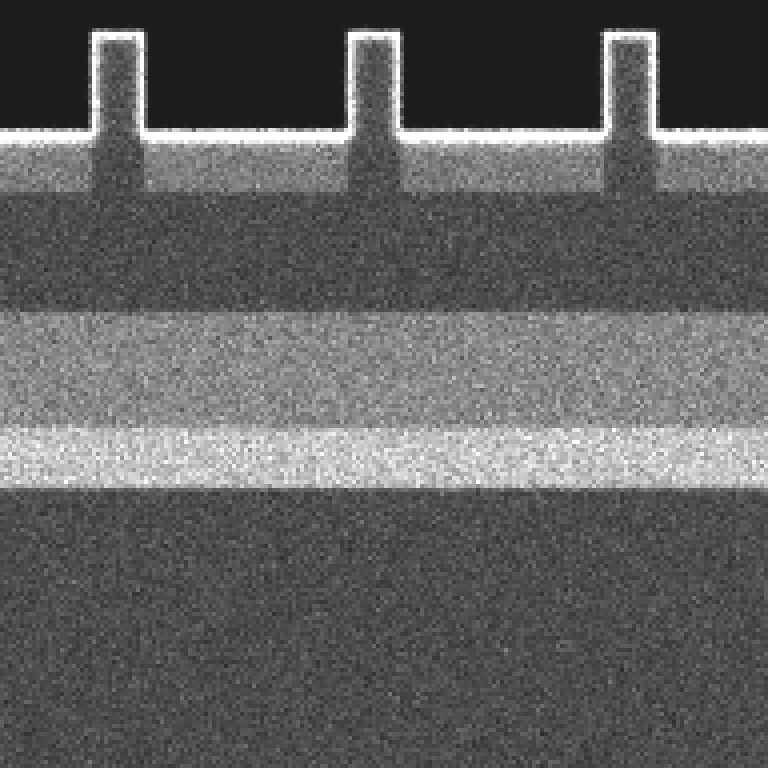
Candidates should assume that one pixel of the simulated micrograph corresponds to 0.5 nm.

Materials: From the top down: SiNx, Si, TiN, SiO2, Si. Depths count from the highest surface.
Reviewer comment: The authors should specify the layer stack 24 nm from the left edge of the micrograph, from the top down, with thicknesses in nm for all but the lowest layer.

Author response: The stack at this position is empty 50, SiNx 30, Si 60, TiN 58, SiO2 30, Si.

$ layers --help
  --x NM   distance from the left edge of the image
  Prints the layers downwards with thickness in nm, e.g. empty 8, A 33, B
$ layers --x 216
empty 50, SiNx 30, Si 60, TiN 58, SiO2 30, Si